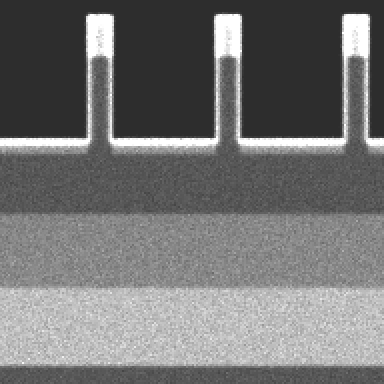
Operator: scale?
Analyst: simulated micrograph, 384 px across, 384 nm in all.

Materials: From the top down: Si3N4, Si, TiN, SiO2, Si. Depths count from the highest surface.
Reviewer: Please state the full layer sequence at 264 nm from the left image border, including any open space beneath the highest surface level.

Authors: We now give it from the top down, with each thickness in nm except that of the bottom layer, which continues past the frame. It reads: empty 124, Si3N4 14, Si 60, TiN 74, SiO2 78, Si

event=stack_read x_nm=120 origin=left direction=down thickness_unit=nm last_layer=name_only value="empty 124, Si3N4 14, Si 60, TiN 74, SiO2 78, Si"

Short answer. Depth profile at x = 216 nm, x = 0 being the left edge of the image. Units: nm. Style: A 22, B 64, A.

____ SiO2 40, Si 158, TiN 74, SiO2 78, Si